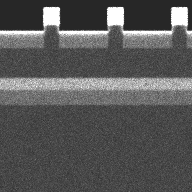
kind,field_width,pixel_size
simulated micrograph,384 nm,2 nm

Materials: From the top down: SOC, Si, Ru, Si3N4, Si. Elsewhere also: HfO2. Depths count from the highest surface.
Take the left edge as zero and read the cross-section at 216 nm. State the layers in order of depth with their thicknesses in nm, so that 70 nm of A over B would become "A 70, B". HfO2 34, Si 106, Ru 24, Si3N4 30, Si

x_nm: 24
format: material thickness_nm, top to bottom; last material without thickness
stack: empty 46, SOC 34, Si 60, Ru 24, Si3N4 30, Si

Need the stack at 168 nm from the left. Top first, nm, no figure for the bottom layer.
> empty 46, SOC 34, Si 60, Ru 24, Si3N4 30, Si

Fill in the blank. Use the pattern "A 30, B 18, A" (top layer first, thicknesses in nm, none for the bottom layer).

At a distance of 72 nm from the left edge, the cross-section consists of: empty 46, SOC 34, Si 60, Ru 24, Si3N4 30, Si